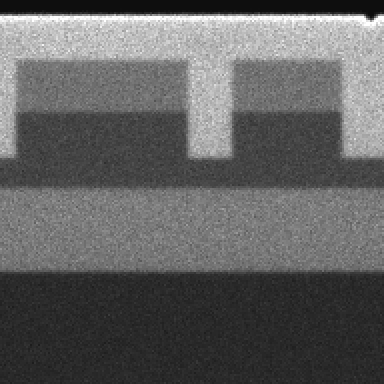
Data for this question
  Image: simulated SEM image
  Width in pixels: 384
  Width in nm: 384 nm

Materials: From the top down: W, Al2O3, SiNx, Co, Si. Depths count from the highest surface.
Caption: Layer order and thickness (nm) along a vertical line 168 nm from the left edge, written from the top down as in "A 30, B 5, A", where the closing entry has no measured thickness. W 44, Al2O3 52, SiNx 76, Co 84, Si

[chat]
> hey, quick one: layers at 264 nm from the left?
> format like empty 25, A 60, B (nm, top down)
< W 44, Al2O3 52, SiNx 76, Co 84, Si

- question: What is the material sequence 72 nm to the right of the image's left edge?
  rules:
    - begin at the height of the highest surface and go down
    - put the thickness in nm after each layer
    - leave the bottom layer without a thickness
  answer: W 44, Al2O3 52, SiNx 76, Co 84, Si